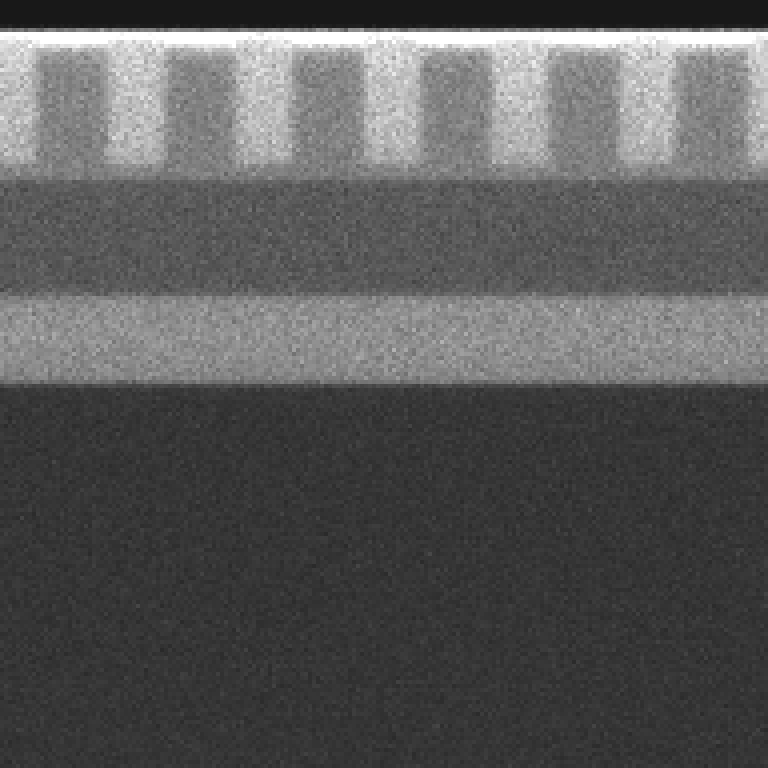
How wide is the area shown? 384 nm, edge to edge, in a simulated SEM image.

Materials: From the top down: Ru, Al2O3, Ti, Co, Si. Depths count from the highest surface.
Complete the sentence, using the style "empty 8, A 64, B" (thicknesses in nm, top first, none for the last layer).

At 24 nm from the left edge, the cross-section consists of Al2O3 74, Ti 58, Co 44, Si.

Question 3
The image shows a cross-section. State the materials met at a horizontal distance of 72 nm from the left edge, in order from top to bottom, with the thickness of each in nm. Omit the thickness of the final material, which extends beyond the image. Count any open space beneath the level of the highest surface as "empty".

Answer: Ru 66, Al2O3 8, Ti 58, Co 44, Si